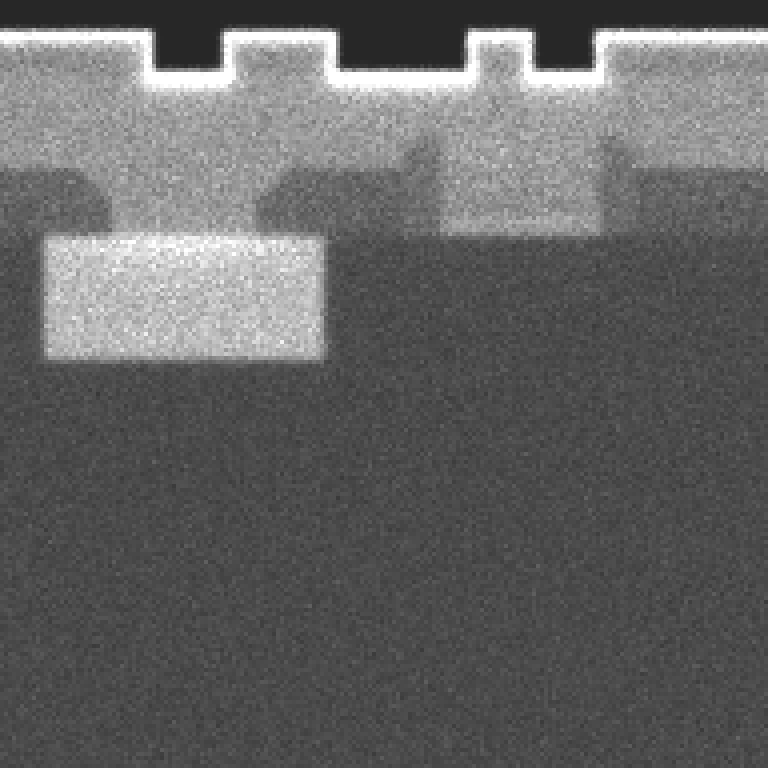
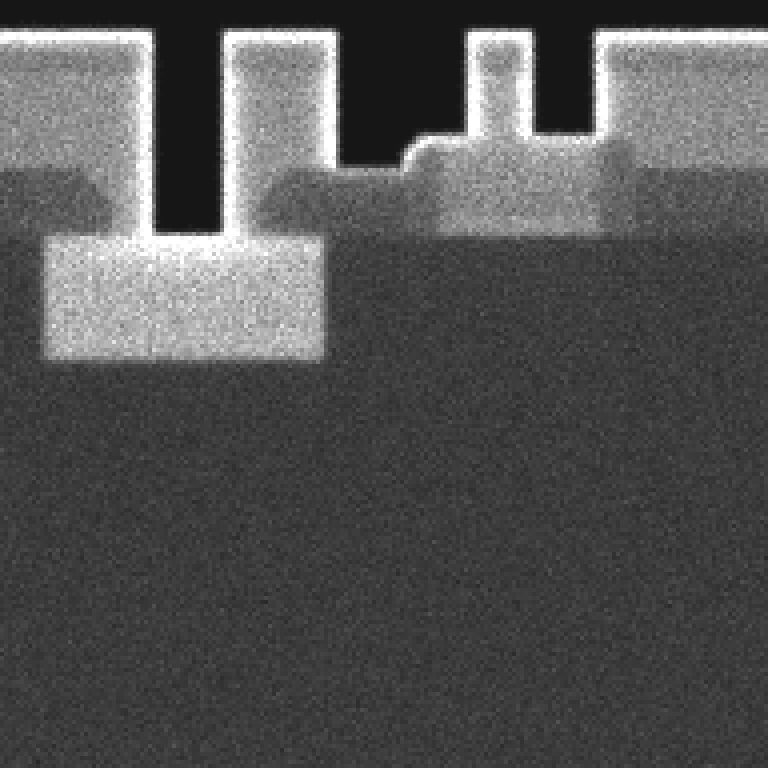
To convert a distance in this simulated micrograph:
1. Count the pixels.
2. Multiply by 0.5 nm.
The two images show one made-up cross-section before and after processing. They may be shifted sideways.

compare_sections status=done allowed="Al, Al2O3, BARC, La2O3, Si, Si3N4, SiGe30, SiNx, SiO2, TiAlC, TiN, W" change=removed material="SiO2"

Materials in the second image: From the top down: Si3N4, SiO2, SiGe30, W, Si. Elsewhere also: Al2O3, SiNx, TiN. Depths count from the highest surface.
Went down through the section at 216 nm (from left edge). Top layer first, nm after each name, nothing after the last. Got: empty 52, SiNx 50, Si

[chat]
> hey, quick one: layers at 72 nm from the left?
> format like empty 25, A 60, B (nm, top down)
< Si3N4 20, SiO2 82, W 62, Si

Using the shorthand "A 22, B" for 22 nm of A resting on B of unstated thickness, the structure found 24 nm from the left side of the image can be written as Si3N4 20, SiO2 48, SiGe30 34, W 62, Si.